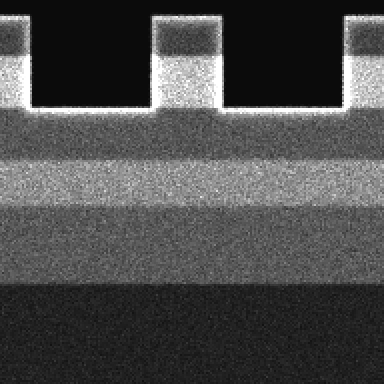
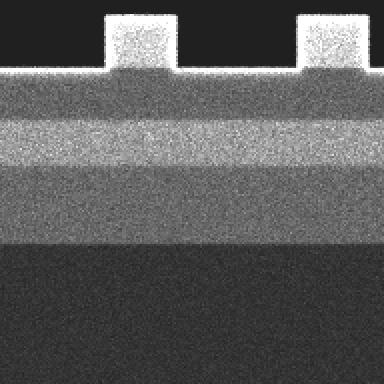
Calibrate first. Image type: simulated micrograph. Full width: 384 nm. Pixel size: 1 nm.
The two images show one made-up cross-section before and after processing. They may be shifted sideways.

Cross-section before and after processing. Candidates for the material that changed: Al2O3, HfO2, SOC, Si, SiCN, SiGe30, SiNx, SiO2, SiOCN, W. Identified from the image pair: SOC (removed).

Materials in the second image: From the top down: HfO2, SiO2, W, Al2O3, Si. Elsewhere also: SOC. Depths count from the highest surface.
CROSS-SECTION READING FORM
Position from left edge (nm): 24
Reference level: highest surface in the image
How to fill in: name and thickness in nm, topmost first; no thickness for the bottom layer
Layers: empty 52, SiO2 52, W 46, Al2O3 78, Si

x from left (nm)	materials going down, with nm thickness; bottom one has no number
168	HfO2 52, SiO2 52, W 46, Al2O3 78, Si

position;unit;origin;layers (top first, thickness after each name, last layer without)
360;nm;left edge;HfO2 52, SiO2 52, W 46, Al2O3 78, Si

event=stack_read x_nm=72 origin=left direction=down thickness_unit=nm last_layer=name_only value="empty 52, SiO2 52, W 46, Al2O3 78, Si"